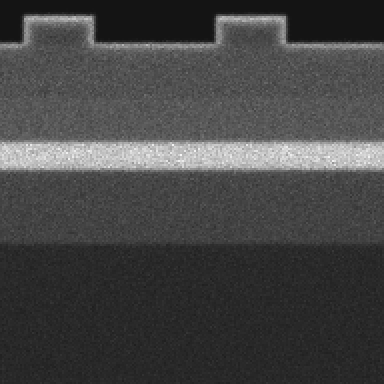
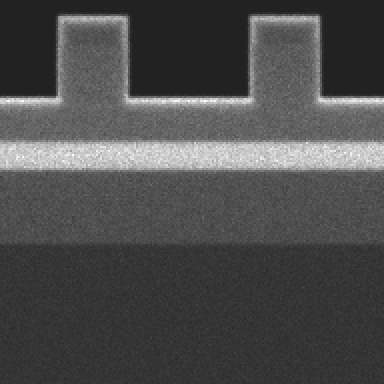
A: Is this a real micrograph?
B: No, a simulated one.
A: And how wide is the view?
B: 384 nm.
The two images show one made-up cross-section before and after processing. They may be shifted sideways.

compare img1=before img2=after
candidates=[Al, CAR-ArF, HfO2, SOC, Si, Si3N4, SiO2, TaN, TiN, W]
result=removed:TiN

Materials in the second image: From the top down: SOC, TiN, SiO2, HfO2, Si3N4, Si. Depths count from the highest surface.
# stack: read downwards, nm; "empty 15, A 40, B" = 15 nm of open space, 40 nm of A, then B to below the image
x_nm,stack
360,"empty 82, SiO2 44, HfO2 28, Si3N4 74, Si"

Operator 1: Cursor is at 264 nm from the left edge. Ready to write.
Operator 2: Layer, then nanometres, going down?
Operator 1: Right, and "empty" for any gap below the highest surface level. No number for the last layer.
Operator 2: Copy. SOC 28, TiN 54, SiO2 44, HfO2 28, Si3N4 74, Si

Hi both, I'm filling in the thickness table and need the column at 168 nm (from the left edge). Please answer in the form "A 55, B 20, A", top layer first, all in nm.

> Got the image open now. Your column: empty 82, SiO2 44, HfO2 28, Si3N4 74, Si